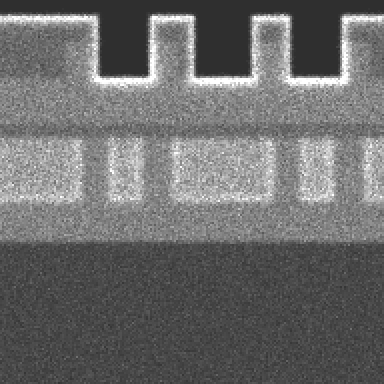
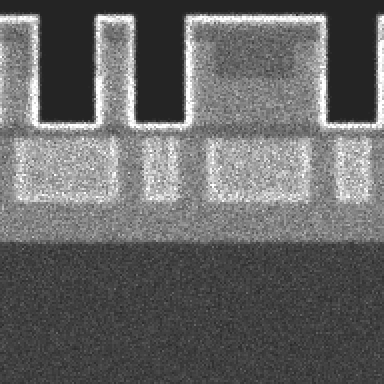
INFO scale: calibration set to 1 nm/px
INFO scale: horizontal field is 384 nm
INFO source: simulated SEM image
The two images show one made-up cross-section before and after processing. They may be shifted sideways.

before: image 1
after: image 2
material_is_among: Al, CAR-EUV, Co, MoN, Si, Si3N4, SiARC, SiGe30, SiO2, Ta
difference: SiO2, removed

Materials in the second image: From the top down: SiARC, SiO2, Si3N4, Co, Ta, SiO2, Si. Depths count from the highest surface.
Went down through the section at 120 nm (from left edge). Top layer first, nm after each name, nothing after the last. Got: SiARC 26, SiO2 82, Si3N4 14, SiO2 104, Si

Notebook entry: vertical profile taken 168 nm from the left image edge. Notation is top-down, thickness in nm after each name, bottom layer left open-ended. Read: empty 108, Si3N4 14, Co 56, Ta 8, SiO2 40, Si